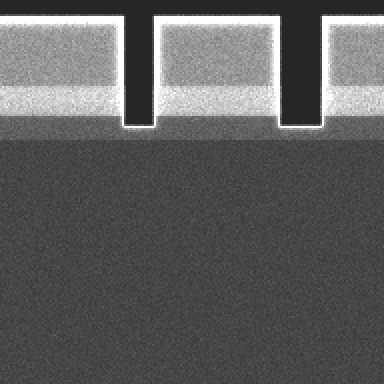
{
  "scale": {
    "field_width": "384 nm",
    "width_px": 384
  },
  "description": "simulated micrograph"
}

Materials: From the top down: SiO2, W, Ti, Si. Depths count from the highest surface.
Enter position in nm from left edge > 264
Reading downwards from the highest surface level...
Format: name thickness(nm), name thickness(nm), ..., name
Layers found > SiO2 70, W 30, Ti 24, Si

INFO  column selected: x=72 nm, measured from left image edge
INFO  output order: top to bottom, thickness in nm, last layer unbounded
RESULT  SiO2 70, W 30, Ti 24, Si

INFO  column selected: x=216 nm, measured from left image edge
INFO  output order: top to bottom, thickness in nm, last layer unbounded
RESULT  SiO2 70, W 30, Ti 24, Si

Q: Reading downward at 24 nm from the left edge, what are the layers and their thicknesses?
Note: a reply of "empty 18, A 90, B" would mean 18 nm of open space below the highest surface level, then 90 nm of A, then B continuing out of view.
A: SiO2 70, W 30, Ti 24, Si